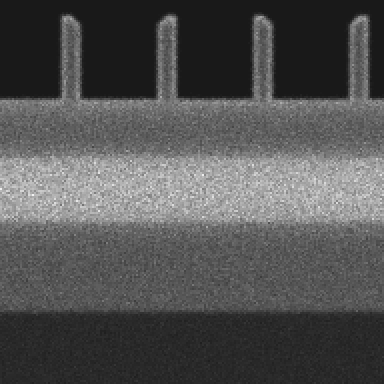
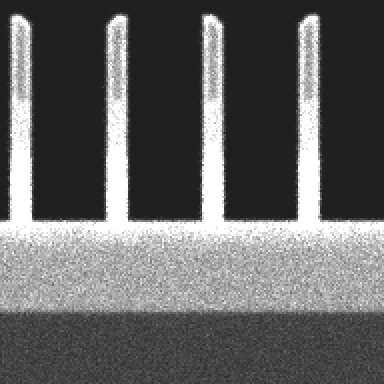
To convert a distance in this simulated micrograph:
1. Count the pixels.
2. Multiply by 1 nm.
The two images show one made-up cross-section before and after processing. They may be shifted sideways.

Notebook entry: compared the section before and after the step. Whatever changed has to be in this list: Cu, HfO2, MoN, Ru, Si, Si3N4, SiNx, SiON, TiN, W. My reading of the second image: HfO2 and W removed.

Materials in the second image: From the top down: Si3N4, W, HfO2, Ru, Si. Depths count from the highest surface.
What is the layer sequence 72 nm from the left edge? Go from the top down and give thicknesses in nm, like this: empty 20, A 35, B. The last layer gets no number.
empty 206, Ru 90, Si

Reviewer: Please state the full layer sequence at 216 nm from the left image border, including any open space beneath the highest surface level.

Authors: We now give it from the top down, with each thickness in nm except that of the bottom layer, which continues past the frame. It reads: empty 4, Si3N4 80, W 58, HfO2 64, Ru 90, Si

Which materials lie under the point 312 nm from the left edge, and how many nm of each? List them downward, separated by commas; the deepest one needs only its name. Si3N4 84, W 58, HfO2 64, Ru 90, Si